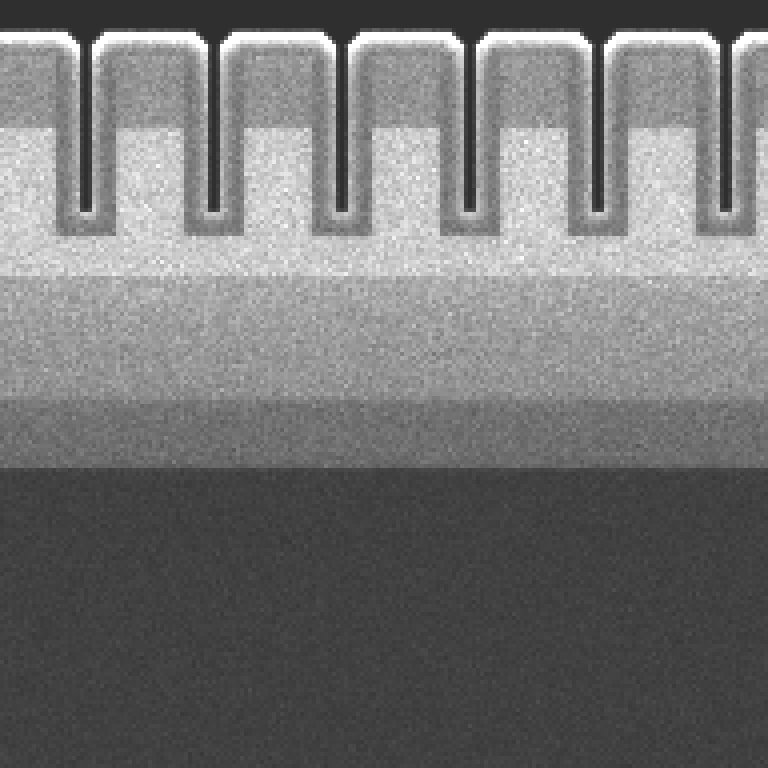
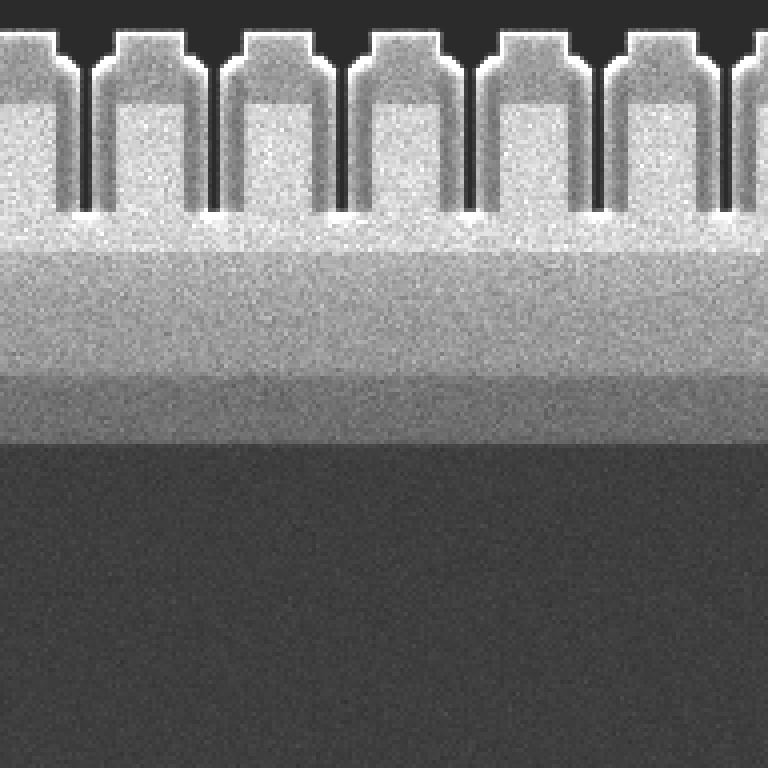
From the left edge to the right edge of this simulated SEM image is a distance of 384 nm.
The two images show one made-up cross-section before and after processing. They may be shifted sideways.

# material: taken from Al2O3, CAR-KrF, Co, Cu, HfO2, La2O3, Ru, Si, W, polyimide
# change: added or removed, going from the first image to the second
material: Al2O3
change: removed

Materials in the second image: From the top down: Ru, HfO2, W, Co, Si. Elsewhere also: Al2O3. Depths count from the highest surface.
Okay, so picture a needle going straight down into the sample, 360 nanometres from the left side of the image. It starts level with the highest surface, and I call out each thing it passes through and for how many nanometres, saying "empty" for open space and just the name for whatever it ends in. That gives empty 90, HfO2 20, W 62, Co 34, Si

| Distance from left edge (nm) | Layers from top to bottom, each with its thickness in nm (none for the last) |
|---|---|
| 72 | Ru 36, HfO2 74, W 62, Co 34, Si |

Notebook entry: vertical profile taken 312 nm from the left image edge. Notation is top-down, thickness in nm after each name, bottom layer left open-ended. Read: empty 12, Al2O3 78, HfO2 20, W 62, Co 34, Si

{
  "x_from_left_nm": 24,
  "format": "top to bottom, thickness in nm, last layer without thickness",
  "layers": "Ru 36, HfO2 74, W 62, Co 34, Si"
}